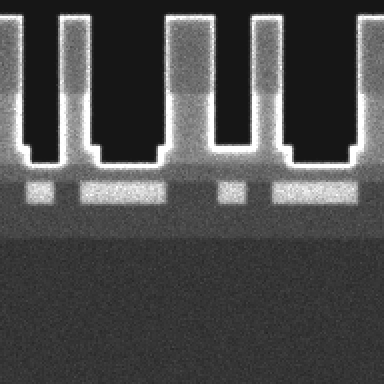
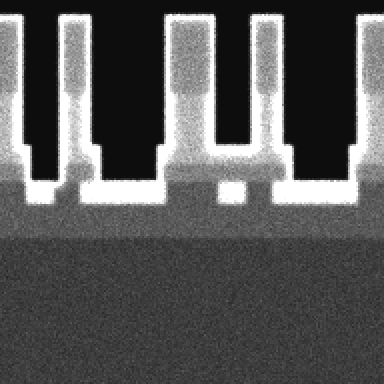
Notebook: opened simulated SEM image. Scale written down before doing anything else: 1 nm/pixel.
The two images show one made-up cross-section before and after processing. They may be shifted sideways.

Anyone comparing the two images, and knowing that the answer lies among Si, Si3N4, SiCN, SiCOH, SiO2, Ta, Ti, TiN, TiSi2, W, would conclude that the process removed Si3N4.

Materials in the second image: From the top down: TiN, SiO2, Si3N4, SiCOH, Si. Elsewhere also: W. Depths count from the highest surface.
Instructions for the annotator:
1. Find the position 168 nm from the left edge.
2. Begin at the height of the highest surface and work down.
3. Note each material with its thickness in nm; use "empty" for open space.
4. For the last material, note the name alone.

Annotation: TiN 78, SiO2 70, Si3N4 18, SiCOH 56, Si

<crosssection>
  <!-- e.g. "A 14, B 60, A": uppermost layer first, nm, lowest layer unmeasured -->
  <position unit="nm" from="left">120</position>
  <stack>empty 166, W 22, SiCOH 34, Si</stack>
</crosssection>